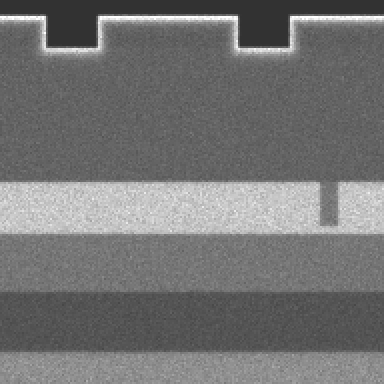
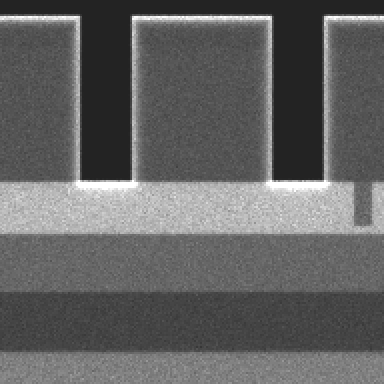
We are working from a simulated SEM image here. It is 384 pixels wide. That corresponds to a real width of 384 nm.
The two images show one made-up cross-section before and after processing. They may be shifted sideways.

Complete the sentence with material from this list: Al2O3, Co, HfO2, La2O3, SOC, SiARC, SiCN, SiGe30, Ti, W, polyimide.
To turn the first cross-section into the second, SOC must be removed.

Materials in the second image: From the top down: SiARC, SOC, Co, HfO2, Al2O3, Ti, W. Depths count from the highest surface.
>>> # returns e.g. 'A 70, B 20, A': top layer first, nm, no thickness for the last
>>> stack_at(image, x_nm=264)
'SiARC 32, SOC 134, HfO2 52, Al2O3 58, Ti 60, W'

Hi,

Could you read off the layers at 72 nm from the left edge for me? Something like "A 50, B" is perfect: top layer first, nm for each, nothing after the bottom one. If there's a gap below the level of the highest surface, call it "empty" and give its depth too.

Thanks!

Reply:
SiARC 32, SOC 134, HfO2 52, Al2O3 58, Ti 60, W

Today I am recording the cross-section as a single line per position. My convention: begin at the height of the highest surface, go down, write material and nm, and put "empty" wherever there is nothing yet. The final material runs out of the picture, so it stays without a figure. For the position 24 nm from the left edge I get SiARC 32, SOC 134, HfO2 52, Al2O3 58, Ti 60, W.